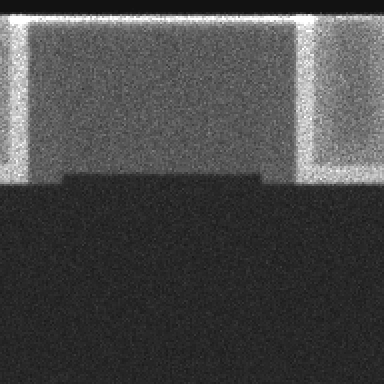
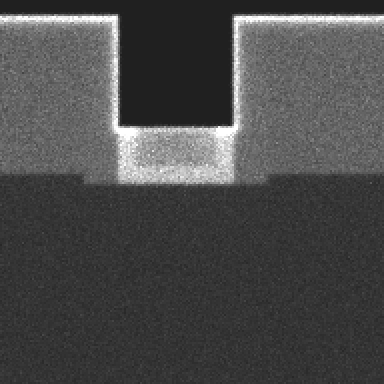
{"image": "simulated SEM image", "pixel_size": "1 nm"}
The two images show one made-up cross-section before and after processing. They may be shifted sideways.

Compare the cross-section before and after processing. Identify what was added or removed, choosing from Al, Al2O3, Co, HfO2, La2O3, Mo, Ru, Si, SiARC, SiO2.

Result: Co and HfO2 and Ru removed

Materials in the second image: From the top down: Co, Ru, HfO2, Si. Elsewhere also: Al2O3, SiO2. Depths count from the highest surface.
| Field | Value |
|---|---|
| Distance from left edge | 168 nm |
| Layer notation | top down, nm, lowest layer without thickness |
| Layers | empty 112, Co 16, Ru 22, HfO2 18, Si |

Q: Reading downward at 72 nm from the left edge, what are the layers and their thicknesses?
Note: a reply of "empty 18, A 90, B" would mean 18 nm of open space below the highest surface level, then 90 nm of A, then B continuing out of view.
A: SiO2 158, Si